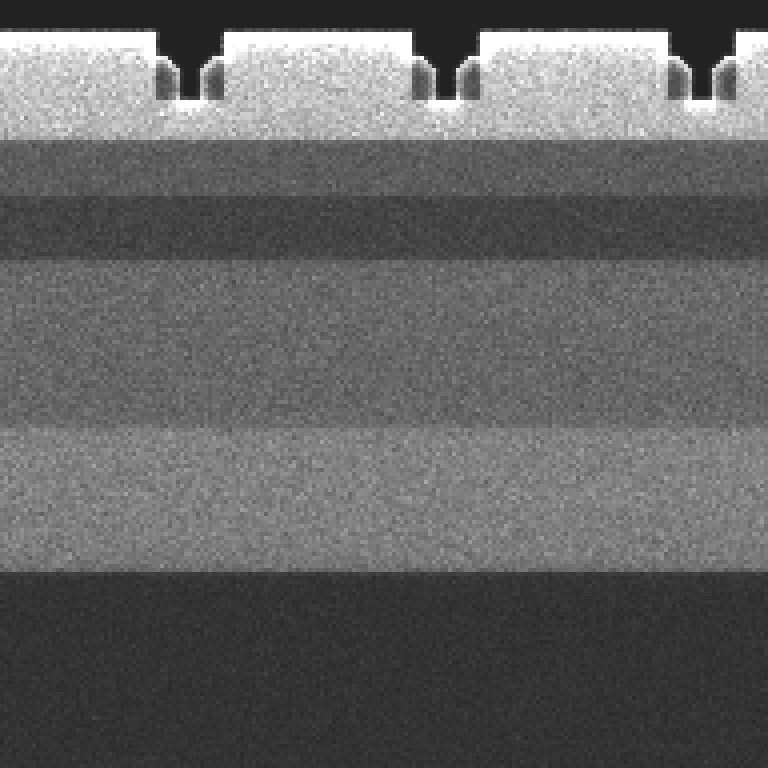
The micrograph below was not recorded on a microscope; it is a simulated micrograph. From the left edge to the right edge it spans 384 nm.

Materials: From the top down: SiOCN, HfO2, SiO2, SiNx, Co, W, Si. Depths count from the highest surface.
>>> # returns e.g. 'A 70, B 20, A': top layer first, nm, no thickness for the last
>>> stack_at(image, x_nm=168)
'HfO2 54, SiO2 28, SiNx 32, Co 84, W 72, Si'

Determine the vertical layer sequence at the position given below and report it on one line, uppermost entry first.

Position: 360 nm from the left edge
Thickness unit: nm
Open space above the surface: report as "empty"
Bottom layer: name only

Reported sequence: empty 14, SiOCN 20, HfO2 20, SiO2 28, SiNx 32, Co 84, W 72, Si